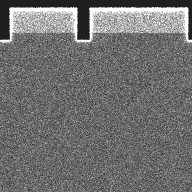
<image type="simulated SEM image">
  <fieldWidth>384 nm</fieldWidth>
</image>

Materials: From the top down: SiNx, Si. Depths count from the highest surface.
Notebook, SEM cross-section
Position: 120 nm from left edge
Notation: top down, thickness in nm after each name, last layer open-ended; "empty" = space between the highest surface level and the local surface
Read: SiNx 50, Si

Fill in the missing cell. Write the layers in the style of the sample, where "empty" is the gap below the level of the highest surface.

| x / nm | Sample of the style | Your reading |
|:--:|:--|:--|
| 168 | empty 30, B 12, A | empty 64, Si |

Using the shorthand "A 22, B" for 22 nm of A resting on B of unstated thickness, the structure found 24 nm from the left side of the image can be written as SiNx 50, Si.